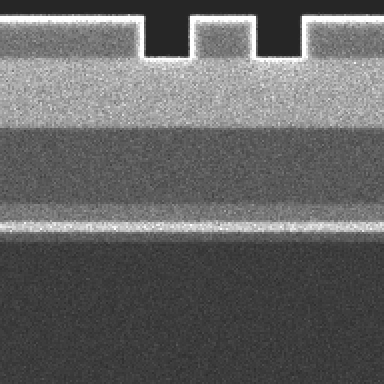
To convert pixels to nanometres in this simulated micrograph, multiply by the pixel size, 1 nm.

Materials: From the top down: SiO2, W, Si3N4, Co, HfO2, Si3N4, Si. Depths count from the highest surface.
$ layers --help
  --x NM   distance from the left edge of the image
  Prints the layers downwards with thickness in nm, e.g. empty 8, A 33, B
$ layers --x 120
SiO2 42, W 70, Si3N4 76, Co 18, HfO2 10, Si3N4 10, Si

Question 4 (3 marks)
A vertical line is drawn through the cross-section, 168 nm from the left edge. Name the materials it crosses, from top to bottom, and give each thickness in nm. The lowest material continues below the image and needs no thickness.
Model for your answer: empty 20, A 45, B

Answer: empty 42, W 70, Si3N4 76, Co 18, HfO2 10, Si3N4 10, Si